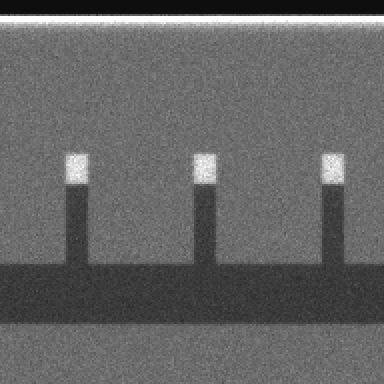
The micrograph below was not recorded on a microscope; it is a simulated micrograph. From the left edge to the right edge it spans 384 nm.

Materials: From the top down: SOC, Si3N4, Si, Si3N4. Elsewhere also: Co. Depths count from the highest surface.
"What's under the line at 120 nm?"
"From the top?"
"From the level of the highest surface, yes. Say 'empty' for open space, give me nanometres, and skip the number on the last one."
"SOC 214, Si3N4 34, Si 60, Si3N4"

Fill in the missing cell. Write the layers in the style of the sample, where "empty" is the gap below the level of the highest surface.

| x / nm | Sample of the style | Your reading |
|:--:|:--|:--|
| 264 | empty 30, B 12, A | SOC 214, Si3N4 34, Si 60, Si3N4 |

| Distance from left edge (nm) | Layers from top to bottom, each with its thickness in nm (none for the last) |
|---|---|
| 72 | SOC 138, Co 30, Si 140, Si3N4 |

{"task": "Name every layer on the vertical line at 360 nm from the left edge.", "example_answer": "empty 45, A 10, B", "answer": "SOC 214, Si3N4 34, Si 60, Si3N4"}